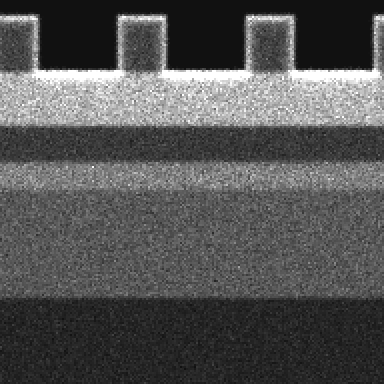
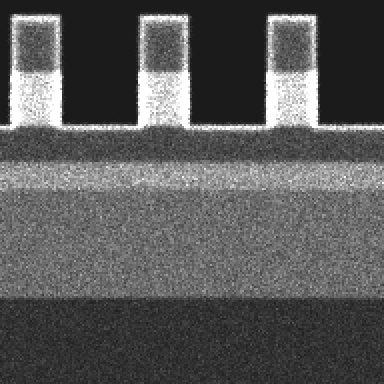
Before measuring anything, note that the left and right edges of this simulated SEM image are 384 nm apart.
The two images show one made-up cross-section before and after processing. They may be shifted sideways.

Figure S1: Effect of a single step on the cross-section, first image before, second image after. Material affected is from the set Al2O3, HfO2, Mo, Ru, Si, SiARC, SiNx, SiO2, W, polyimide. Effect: removed HfO2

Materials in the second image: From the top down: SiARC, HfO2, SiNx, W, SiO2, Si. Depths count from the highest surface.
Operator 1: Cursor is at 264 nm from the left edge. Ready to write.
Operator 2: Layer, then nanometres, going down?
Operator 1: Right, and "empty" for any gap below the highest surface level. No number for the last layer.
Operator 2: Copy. empty 110, SiNx 36, W 28, SiO2 108, Si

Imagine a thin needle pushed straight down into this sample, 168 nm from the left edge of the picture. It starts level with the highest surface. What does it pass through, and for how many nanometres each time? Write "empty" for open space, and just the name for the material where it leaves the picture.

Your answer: SiARC 56, HfO2 54, SiNx 36, W 28, SiO2 108, Si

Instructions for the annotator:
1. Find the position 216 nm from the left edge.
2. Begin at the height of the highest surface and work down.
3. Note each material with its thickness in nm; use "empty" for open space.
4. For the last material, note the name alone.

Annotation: empty 110, SiNx 36, W 28, SiO2 108, Si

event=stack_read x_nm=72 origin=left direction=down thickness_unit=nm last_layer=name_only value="empty 110, SiNx 36, W 28, SiO2 108, Si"